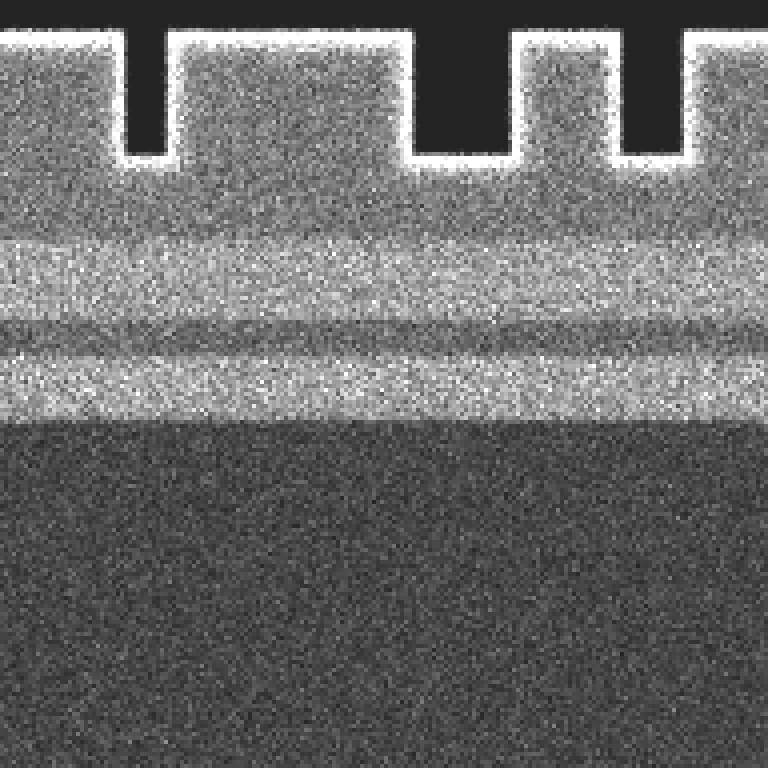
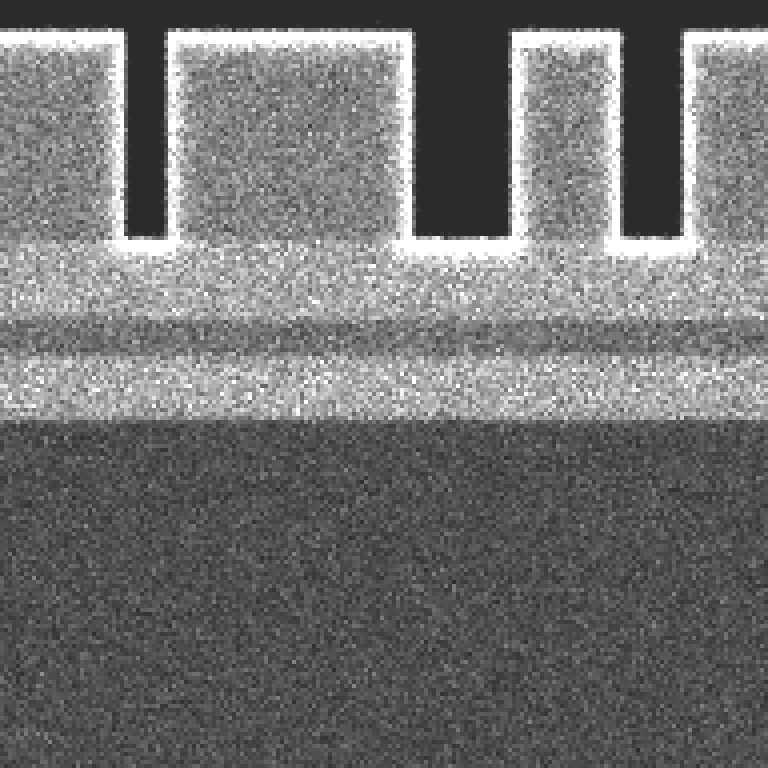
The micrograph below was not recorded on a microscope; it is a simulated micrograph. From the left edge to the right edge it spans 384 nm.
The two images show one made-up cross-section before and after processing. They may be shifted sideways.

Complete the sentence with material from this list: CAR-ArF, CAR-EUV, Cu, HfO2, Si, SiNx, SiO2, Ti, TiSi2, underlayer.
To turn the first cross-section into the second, underlayer must be removed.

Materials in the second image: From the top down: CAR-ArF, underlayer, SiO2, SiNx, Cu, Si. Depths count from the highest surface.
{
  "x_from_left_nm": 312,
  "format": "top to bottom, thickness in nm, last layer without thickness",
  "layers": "empty 104, SiO2 40, SiNx 18, Cu 32, Si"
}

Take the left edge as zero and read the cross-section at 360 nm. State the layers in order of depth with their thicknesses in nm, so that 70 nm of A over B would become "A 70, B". CAR-ArF 62, underlayer 42, SiO2 40, SiNx 18, Cu 32, Si